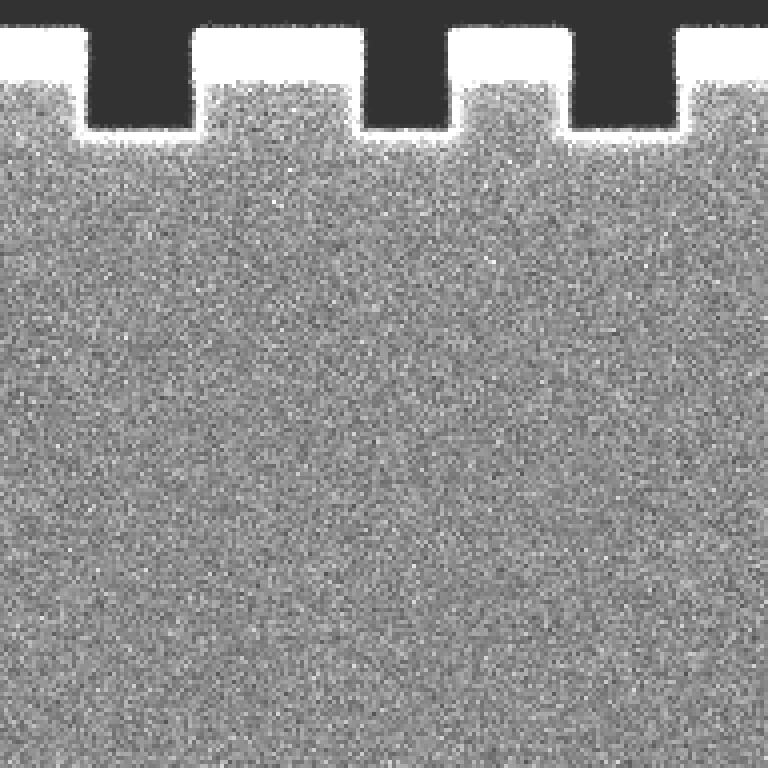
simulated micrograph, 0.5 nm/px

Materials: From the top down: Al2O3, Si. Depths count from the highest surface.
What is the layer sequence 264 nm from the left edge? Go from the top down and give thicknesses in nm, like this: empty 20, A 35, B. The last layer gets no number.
Al2O3 24, Si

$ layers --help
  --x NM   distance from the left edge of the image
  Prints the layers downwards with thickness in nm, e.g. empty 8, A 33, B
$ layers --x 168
Al2O3 24, Si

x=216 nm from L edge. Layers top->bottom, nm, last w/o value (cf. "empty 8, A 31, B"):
empty 50, Si